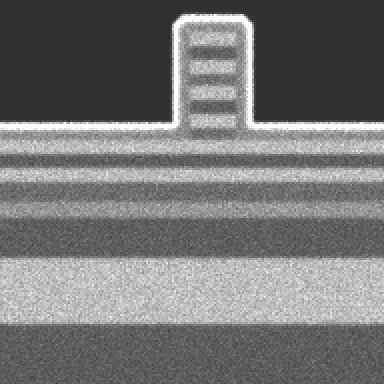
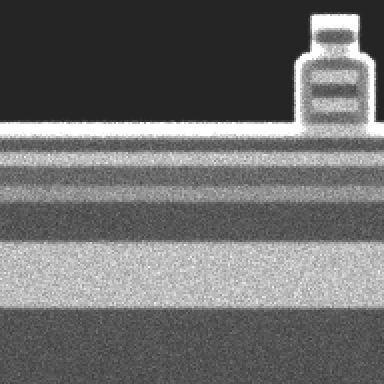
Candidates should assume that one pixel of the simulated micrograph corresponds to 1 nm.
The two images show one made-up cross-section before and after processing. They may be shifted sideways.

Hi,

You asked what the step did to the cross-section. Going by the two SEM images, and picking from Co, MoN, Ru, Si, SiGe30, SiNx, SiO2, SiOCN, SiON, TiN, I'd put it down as SiNx, removed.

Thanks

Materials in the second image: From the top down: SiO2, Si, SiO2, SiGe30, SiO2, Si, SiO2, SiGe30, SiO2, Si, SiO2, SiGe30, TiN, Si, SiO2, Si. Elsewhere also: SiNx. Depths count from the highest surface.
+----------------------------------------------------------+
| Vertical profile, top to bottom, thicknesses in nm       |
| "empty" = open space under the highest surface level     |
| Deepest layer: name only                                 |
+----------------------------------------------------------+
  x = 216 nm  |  empty 108, SiO2 14, Si 14, SiO2 14, SiGe30 20, TiN 16, Si 40, SiO2 66, Si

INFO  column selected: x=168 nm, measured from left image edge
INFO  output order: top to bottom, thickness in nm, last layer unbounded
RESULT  empty 108, SiO2 14, Si 14, SiO2 14, SiGe30 20, TiN 16, Si 40, SiO2 66, Si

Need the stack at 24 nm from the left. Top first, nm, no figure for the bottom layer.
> empty 108, SiO2 14, Si 14, SiO2 14, SiGe30 20, TiN 16, Si 40, SiO2 66, Si